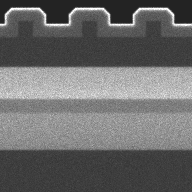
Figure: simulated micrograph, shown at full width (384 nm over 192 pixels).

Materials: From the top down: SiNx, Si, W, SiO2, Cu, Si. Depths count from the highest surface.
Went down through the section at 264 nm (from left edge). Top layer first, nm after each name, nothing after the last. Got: empty 32, SiNx 26, Si 60, W 64, SiO2 28, Cu 74, Si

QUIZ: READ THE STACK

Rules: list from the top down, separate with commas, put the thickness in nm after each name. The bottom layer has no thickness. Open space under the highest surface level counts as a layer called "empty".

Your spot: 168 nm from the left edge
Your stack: SiNx 26, Si 92, W 64, SiO2 28, Cu 74, Si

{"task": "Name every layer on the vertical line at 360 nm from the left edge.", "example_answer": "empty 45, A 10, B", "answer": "empty 32, SiNx 26, Si 60, W 64, SiO2 28, Cu 74, Si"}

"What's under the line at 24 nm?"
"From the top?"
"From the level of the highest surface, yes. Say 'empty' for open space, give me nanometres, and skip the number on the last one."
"SiNx 58, Si 60, W 64, SiO2 28, Cu 74, Si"